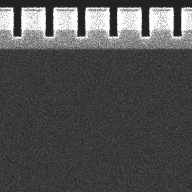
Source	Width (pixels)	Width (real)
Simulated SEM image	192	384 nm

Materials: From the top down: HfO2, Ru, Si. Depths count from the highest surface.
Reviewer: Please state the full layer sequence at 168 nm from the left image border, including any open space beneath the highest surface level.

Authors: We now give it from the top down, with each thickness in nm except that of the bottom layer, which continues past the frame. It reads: empty 58, Ru 24, Si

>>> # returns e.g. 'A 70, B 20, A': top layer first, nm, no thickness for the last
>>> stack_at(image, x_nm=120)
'HfO2 44, Ru 38, Si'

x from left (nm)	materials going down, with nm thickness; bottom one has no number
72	HfO2 44, Ru 38, Si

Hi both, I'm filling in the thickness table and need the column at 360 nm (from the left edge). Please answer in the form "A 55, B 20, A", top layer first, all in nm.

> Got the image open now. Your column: empty 58, Ru 24, Si